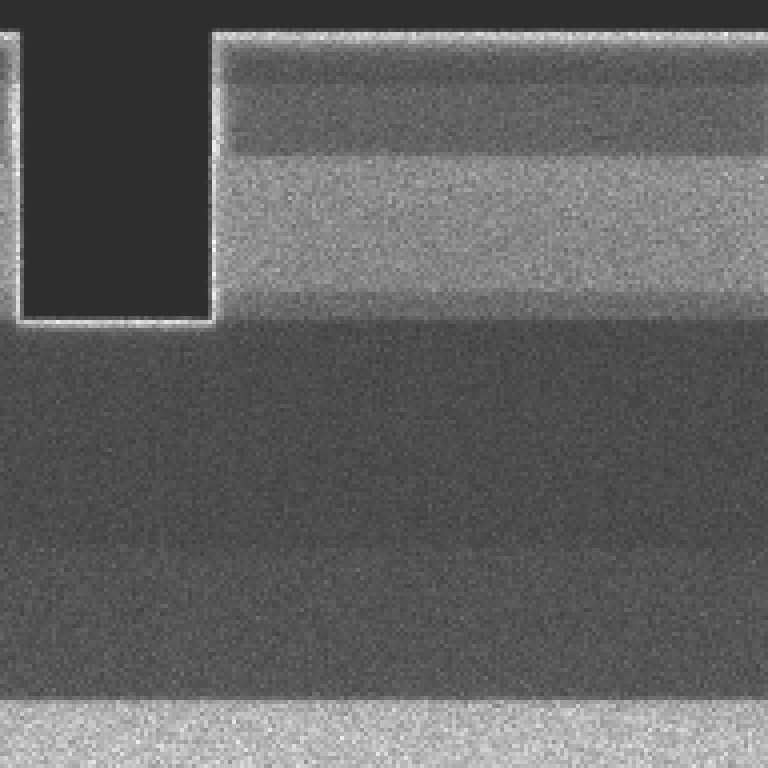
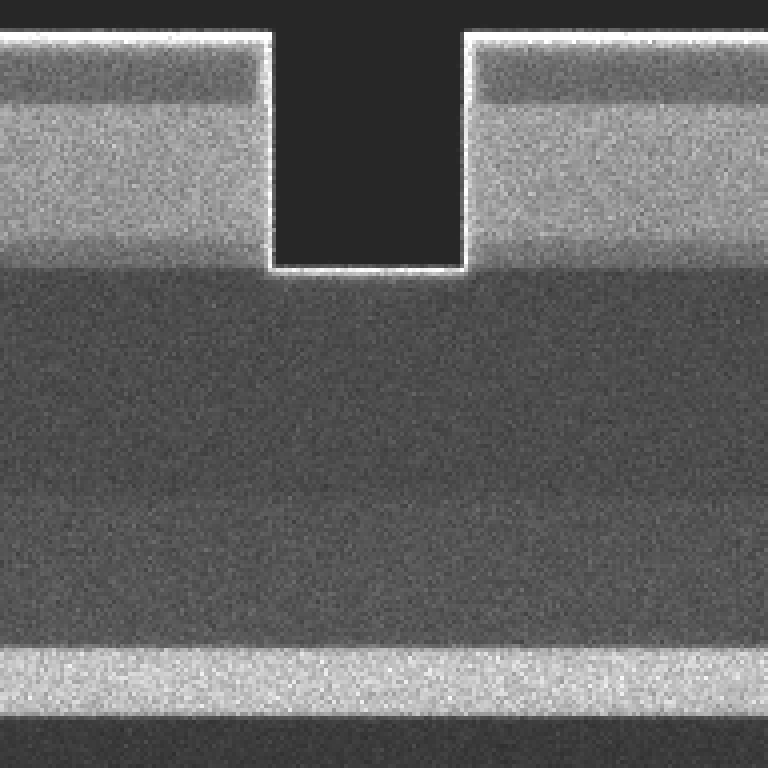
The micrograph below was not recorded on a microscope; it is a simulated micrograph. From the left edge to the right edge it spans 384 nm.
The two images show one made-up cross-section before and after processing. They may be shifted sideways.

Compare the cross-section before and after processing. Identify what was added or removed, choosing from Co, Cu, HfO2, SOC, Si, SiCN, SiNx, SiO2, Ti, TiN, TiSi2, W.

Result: SOC removed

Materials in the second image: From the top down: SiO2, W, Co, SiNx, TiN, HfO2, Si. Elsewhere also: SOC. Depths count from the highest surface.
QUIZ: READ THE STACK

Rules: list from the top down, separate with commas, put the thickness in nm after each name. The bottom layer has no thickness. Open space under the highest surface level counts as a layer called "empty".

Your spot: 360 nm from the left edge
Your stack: SiO2 36, W 68, Co 14, SiNx 114, TiN 76, HfO2 34, Si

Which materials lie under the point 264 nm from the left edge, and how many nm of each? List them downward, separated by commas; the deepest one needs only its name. SiO2 36, W 68, Co 14, SiNx 114, TiN 76, HfO2 34, Si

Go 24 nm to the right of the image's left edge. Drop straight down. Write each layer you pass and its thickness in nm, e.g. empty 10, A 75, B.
SiO2 36, W 68, Co 14, SiNx 114, TiN 76, HfO2 34, Si